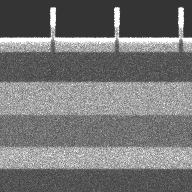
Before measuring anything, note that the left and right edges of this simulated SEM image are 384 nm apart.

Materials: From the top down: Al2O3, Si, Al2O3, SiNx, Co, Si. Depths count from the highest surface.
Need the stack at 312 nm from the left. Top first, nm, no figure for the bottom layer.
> empty 60, Al2O3 28, Si 60, Al2O3 66, SiNx 64, Co 44, Si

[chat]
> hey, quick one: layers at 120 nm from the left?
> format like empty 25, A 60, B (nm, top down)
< empty 60, Al2O3 28, Si 60, Al2O3 66, SiNx 64, Co 44, Si